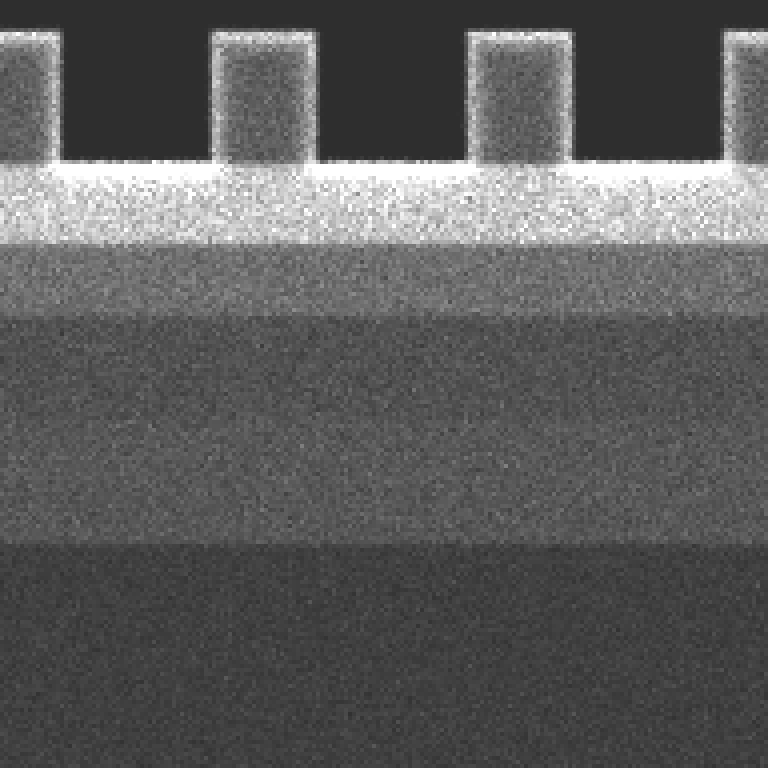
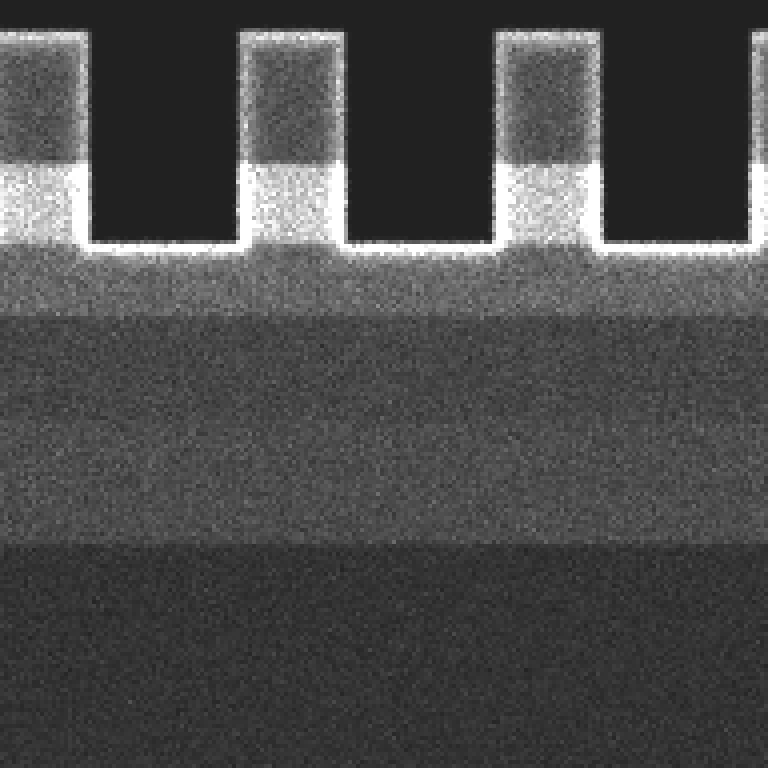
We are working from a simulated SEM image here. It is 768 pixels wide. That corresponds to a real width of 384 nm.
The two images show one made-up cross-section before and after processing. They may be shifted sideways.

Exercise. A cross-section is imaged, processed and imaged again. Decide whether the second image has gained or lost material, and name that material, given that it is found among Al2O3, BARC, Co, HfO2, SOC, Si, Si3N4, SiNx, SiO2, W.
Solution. removed: HfO2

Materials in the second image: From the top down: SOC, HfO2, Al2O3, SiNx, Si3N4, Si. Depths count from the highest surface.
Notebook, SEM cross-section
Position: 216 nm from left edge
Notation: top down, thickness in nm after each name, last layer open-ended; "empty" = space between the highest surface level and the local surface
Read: empty 106, Al2O3 36, SiNx 52, Si3N4 62, Si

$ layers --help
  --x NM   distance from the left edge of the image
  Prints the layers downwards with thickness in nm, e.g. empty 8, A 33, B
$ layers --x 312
empty 106, Al2O3 36, SiNx 52, Si3N4 62, Si